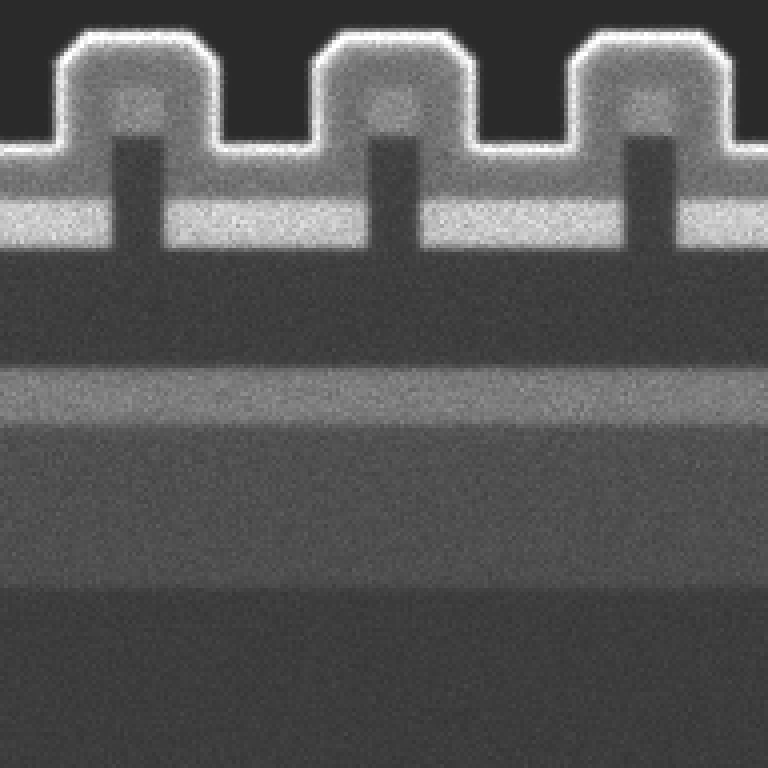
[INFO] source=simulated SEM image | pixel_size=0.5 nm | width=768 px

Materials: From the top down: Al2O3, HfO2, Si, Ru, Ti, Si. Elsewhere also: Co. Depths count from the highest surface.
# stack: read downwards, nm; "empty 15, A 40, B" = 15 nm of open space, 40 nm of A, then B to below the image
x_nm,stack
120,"empty 56, Al2O3 28, HfO2 24, Si 60, Ru 28, Ti 82, Si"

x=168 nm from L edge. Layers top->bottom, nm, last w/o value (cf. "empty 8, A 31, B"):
empty 2, Al2O3 82, HfO2 24, Si 60, Ru 28, Ti 82, Si